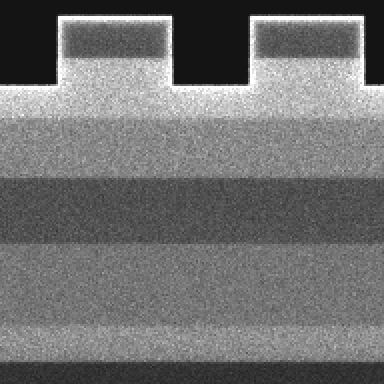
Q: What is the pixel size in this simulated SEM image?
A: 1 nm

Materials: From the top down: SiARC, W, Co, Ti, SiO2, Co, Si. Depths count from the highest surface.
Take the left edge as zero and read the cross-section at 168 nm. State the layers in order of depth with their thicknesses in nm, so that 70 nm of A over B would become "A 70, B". SiARC 42, W 60, Co 60, Ti 66, SiO2 82, Co 36, Si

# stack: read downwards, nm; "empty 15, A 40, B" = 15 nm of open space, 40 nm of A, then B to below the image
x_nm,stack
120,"SiARC 42, W 60, Co 60, Ti 66, SiO2 82, Co 36, Si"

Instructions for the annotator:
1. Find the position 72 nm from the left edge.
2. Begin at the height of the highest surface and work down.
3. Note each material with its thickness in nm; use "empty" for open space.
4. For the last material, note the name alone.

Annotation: SiARC 42, W 60, Co 60, Ti 66, SiO2 82, Co 36, Si